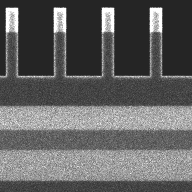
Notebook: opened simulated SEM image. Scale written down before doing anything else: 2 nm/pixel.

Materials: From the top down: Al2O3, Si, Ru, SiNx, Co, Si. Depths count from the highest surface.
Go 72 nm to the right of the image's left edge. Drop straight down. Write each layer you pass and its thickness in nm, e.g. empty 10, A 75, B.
empty 136, Si 60, Ru 48, SiNx 40, Co 62, Si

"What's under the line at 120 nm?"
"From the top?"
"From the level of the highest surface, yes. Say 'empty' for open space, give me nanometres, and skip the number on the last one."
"Al2O3 48, Si 148, Ru 48, SiNx 40, Co 62, Si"